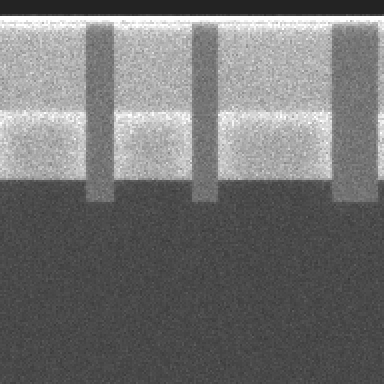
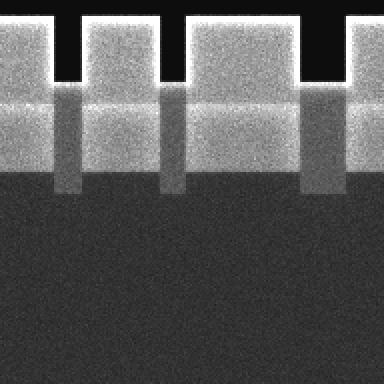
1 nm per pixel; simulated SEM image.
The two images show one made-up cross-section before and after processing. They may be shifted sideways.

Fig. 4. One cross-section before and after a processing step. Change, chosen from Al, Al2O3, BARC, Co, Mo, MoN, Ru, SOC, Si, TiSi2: SOC removed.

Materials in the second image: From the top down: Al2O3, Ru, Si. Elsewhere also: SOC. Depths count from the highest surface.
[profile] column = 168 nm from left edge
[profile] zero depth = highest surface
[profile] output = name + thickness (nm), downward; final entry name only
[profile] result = empty 66, SOC 112, Si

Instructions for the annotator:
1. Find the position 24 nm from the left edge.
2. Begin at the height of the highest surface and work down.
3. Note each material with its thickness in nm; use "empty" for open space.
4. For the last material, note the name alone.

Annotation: Al2O3 88, Ru 68, Si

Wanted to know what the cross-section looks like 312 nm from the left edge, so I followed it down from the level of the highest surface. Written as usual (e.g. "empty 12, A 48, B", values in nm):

empty 66, SOC 112, Si